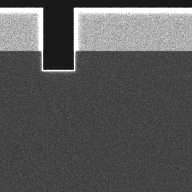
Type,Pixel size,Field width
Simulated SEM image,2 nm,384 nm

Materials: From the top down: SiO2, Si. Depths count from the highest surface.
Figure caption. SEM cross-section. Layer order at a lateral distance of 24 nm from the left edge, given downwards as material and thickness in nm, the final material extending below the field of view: SiO2 86, Si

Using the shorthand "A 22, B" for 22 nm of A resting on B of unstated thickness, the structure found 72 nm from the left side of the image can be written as SiO2 86, Si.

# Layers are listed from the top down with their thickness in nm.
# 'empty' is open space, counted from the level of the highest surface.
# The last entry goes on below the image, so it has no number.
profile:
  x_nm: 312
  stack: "SiO2 86, Si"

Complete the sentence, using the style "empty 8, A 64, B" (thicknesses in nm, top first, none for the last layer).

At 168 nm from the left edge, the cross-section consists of SiO2 86, Si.